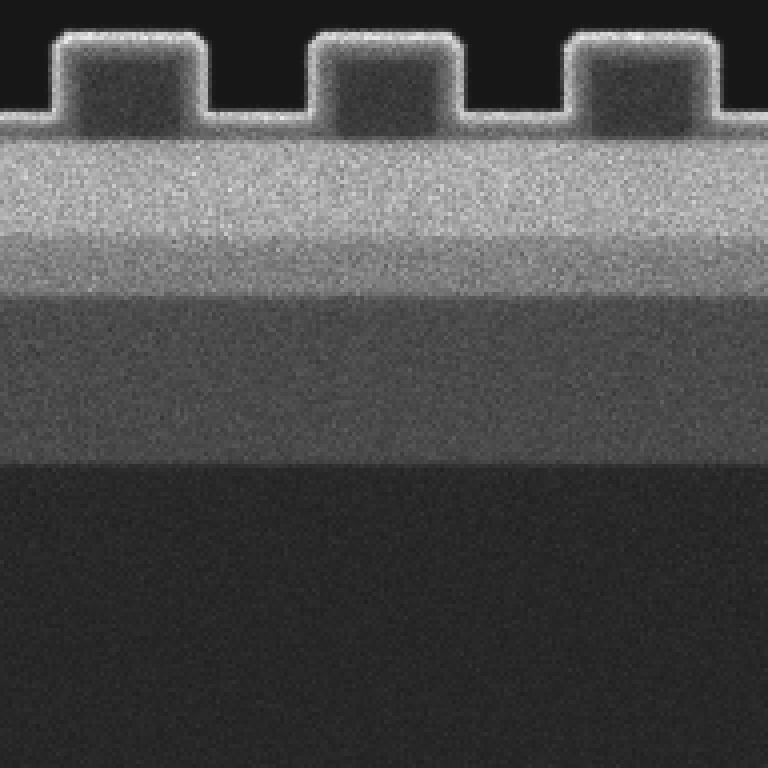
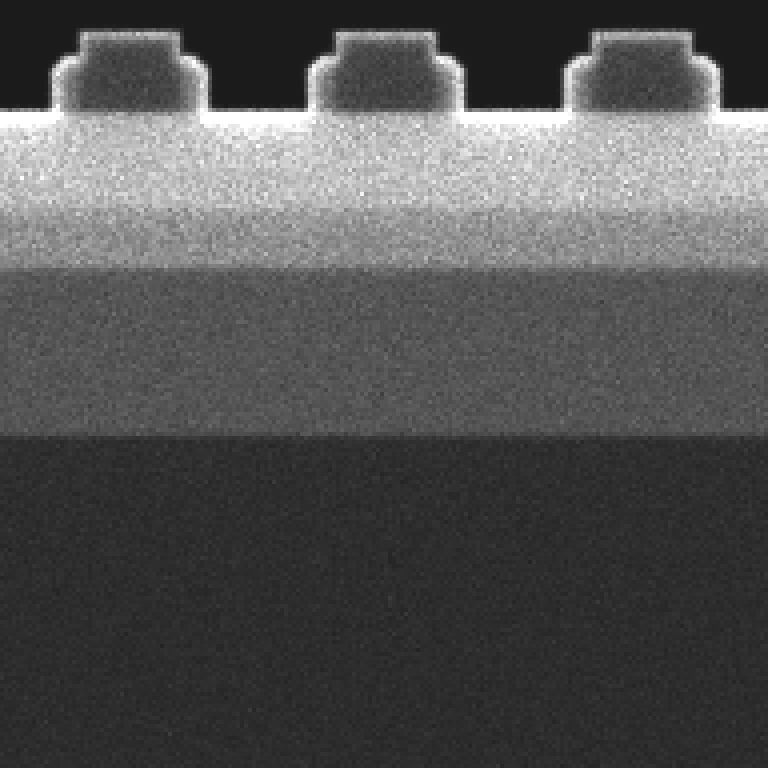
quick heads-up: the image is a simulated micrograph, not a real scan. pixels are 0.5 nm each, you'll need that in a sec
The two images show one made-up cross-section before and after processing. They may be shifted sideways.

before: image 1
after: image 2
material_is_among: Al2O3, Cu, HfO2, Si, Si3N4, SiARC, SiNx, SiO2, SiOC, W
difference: Al2O3, removed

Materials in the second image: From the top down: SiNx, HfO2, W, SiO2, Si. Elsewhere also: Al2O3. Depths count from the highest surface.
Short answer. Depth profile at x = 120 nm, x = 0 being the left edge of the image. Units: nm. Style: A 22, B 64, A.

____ empty 40, HfO2 48, W 30, SiO2 84, Si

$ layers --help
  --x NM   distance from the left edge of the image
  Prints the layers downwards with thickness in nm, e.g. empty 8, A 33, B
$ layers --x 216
SiNx 40, HfO2 48, W 30, SiO2 84, Si